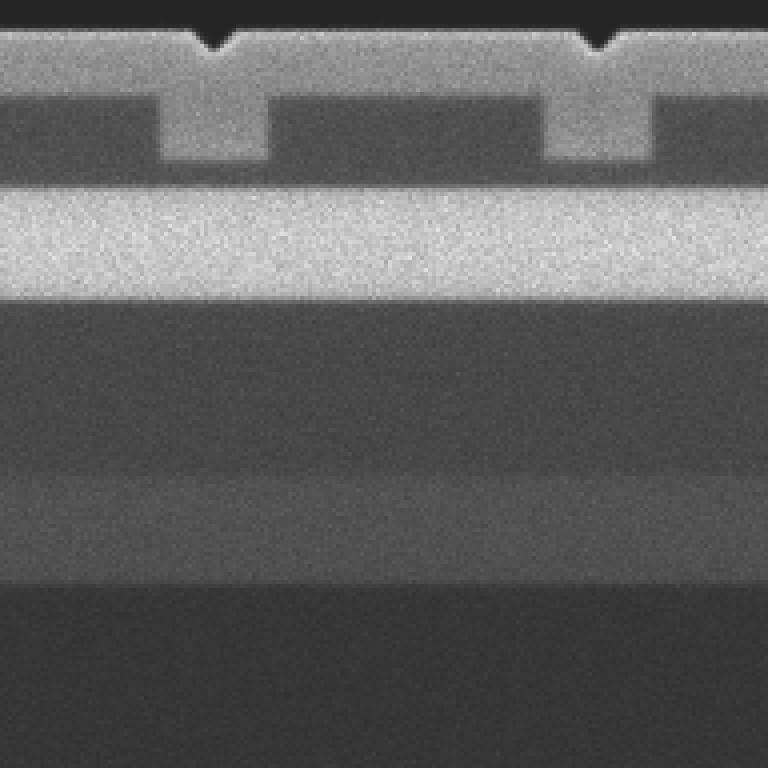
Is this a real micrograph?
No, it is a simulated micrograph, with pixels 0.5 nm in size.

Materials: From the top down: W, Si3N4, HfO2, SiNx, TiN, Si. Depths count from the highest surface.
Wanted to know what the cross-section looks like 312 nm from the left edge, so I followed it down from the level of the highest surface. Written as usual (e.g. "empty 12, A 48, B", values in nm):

W 64, Si3N4 14, HfO2 56, SiNx 88, TiN 54, Si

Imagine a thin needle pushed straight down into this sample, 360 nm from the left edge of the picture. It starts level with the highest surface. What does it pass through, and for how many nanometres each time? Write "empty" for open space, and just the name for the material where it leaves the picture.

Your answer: W 32, Si3N4 46, HfO2 56, SiNx 88, TiN 54, Si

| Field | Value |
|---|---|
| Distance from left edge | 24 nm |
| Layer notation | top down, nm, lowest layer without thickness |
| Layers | W 32, Si3N4 46, HfO2 56, SiNx 88, TiN 54, Si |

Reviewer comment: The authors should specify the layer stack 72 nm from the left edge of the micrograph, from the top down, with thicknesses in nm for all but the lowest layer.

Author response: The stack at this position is W 32, Si3N4 46, HfO2 56, SiNx 88, TiN 54, Si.